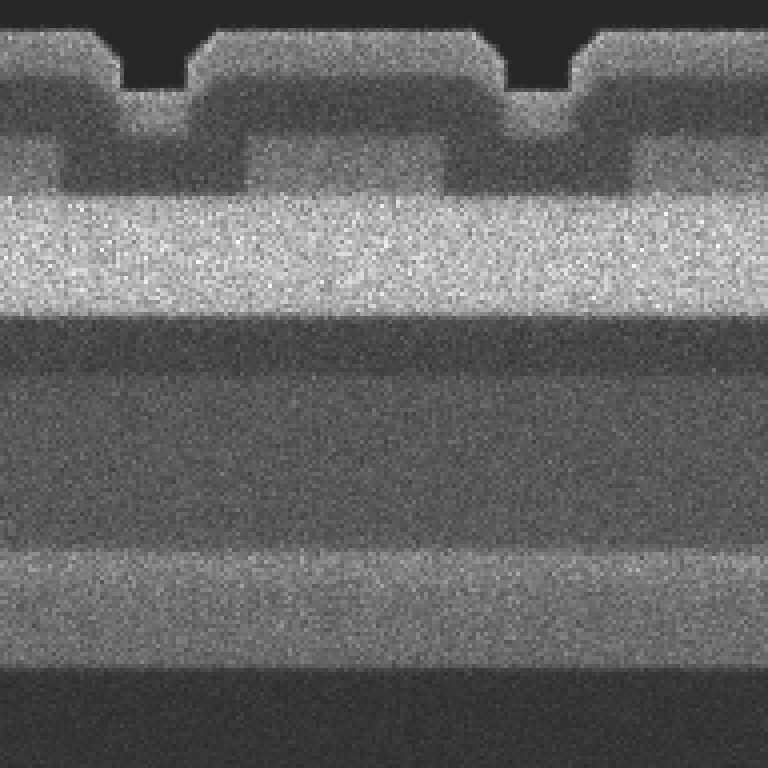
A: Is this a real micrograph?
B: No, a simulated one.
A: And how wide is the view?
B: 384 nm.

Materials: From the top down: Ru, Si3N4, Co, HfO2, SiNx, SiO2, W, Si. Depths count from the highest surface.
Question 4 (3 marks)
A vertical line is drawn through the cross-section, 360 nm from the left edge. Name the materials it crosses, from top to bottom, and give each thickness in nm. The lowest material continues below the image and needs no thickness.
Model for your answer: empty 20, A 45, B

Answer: Ru 22, Si3N4 30, Co 30, HfO2 60, SiNx 30, SiO2 88, W 58, Si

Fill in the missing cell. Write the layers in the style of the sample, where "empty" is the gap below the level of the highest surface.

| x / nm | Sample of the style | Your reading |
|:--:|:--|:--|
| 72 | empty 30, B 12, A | empty 30, Ru 22, Si3N4 30, HfO2 60, SiNx 30, SiO2 88, W 58, Si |